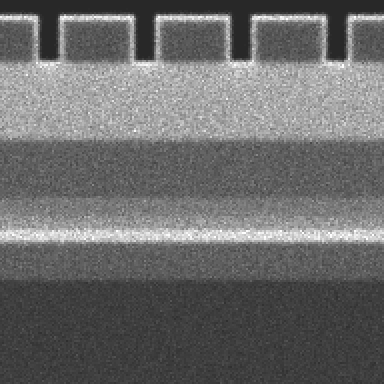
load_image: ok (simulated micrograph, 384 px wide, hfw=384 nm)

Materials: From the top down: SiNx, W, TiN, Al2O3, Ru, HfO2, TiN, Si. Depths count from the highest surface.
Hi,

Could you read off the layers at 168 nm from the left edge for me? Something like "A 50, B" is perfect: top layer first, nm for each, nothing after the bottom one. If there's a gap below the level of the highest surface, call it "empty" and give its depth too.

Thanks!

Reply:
SiNx 46, W 78, TiN 58, Al2O3 18, Ru 14, HfO2 12, TiN 38, Si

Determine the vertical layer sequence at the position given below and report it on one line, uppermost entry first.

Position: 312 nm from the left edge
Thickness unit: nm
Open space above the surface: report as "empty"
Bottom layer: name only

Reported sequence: SiNx 46, W 78, TiN 58, Al2O3 18, Ru 14, HfO2 12, TiN 38, Si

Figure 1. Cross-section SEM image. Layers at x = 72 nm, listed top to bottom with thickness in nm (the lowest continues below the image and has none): SiNx 46, W 78, TiN 58, Al2O3 18, Ru 14, HfO2 12, TiN 38, Si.